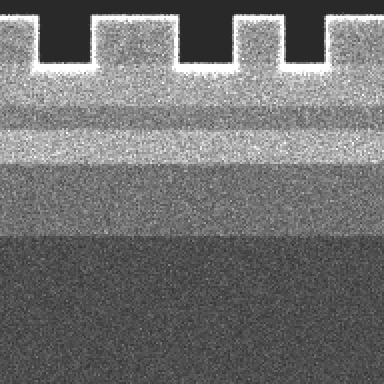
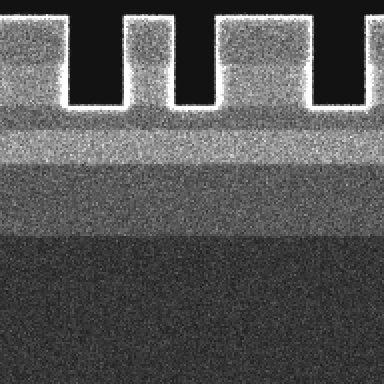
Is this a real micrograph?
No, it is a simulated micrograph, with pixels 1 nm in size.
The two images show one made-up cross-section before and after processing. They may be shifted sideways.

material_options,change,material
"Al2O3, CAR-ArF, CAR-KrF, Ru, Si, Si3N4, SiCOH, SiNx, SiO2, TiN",removed,SiO2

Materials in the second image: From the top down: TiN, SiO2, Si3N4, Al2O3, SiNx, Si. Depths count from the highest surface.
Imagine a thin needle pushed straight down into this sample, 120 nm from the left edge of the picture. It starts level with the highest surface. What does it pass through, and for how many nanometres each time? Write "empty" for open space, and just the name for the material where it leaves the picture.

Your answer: empty 90, Si3N4 24, Al2O3 34, SiNx 72, Si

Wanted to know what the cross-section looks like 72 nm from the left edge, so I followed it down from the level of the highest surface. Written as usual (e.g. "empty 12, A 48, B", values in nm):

empty 90, Si3N4 24, Al2O3 34, SiNx 72, Si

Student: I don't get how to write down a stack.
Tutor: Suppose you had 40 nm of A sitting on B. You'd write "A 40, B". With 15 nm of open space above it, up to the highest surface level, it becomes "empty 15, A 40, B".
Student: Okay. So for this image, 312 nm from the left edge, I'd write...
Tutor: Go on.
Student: empty 90, Si3N4 24, Al2O3 34, SiNx 72, Si